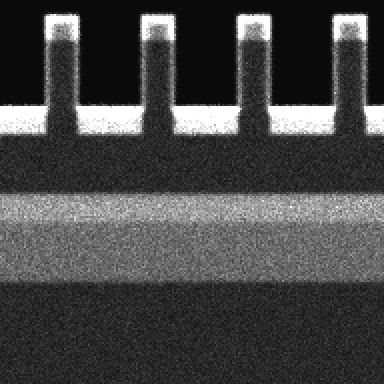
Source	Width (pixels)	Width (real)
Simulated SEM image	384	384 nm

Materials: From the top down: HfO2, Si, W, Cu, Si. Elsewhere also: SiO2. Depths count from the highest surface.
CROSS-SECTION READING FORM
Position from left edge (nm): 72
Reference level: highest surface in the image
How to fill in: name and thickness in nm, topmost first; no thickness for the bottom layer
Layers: SiO2 24, Si 154, W 28, Cu 60, Si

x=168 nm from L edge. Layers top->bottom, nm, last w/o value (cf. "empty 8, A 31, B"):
SiO2 24, Si 154, W 28, Cu 60, Si